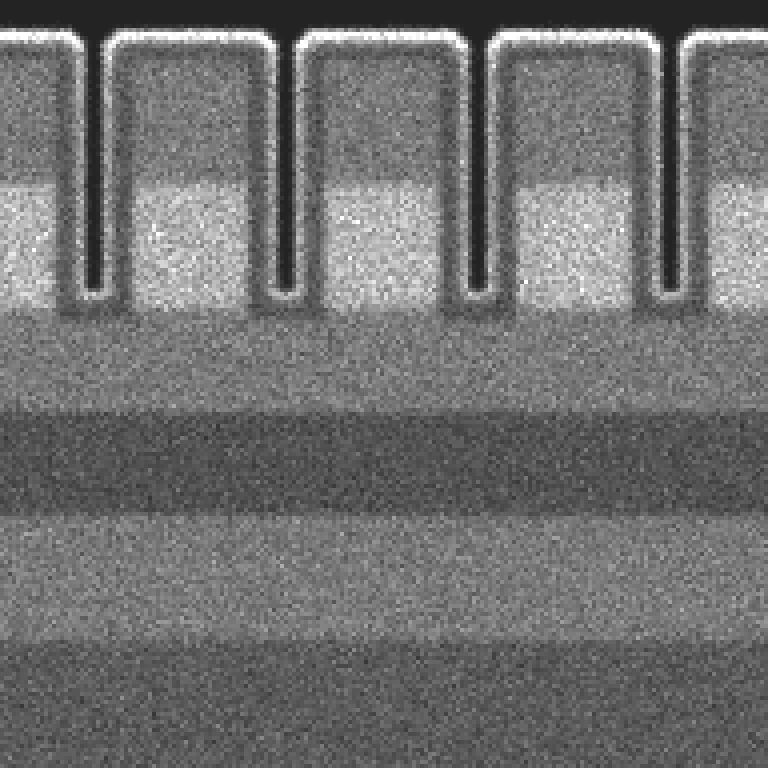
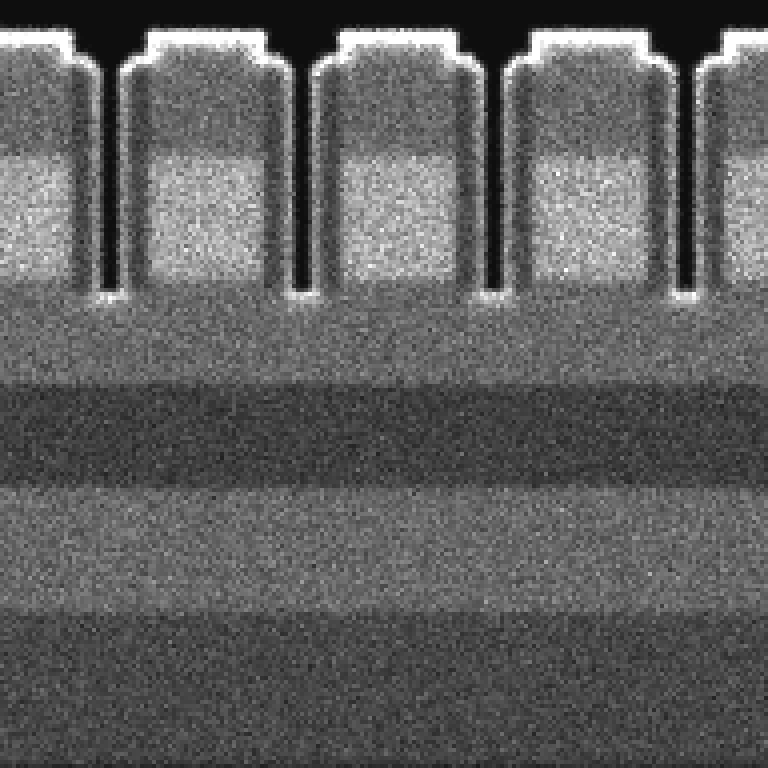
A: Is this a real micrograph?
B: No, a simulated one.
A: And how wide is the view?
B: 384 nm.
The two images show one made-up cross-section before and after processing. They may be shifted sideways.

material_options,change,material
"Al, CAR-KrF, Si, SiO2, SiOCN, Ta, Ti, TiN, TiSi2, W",removed,SiOCN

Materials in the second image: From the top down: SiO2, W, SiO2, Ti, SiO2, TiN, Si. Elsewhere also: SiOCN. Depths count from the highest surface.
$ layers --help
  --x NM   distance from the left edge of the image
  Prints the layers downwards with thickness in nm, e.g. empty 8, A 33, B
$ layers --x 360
empty 12, SiOCN 118, SiO2 46, Ti 52, SiO2 62, TiN 76, Si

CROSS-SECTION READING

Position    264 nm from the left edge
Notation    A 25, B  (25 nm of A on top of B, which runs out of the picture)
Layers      empty 12, SiOCN 118, SiO2 46, Ti 52, SiO2 62, TiN 76, Si